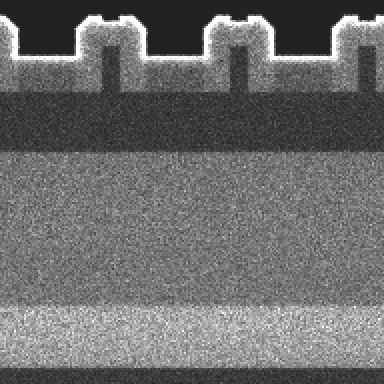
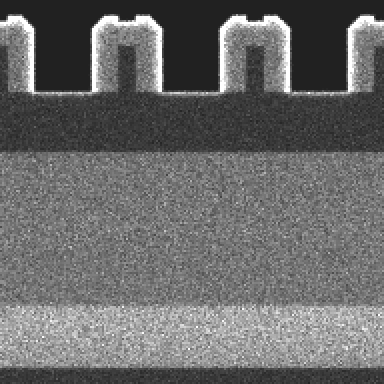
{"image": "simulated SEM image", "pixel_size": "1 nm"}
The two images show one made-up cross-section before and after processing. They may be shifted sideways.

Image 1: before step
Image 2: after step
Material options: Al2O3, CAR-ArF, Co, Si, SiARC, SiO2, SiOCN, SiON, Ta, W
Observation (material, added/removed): SiARC, removed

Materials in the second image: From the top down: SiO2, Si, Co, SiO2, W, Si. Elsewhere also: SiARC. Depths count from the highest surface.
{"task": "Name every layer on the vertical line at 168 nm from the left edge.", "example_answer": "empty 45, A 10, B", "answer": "empty 76, Si 60, Co 90, SiO2 64, W 62, Si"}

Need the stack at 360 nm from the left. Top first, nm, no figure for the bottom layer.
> SiO2 76, Si 60, Co 90, SiO2 64, W 62, Si